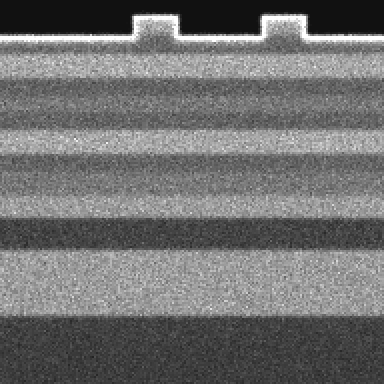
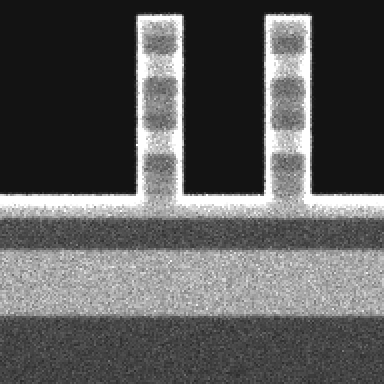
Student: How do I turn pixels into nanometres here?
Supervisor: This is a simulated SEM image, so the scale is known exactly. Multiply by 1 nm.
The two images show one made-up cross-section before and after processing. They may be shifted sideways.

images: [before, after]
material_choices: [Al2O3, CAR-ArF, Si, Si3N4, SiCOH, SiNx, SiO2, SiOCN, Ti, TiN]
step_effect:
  removed: Al2O3 and Si3N4 and SiOCN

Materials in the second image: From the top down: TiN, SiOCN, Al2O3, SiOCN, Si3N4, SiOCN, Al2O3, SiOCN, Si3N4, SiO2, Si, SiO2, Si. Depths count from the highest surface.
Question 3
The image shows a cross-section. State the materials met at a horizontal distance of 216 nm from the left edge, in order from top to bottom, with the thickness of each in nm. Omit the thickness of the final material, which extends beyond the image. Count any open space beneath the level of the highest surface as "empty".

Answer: empty 180, SiO2 22, Si 32, SiO2 66, Si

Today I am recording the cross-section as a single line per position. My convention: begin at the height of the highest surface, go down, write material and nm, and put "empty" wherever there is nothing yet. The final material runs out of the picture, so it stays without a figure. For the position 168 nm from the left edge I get TiN 20, SiOCN 18, Al2O3 24, SiOCN 18, Si3N4 16, SiOCN 18, Al2O3 24, SiOCN 18, Si3N4 24, SiO2 22, Si 32, SiO2 66, Si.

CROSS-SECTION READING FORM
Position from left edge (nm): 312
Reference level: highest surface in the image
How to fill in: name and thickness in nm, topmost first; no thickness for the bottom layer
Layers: empty 180, SiO2 22, Si 32, SiO2 66, Si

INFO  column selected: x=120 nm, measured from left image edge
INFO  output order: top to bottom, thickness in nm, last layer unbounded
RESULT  empty 180, SiO2 22, Si 32, SiO2 66, Si